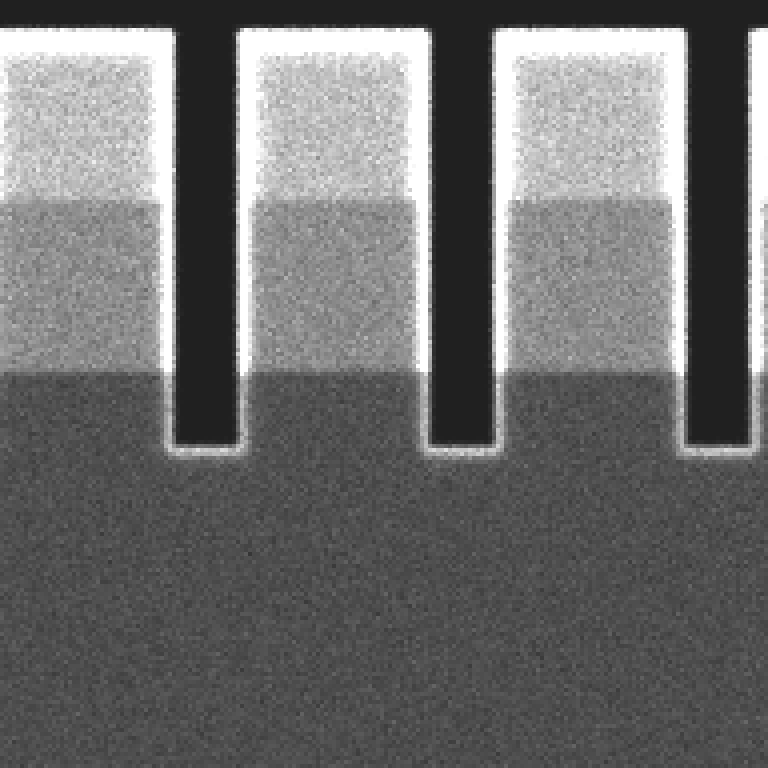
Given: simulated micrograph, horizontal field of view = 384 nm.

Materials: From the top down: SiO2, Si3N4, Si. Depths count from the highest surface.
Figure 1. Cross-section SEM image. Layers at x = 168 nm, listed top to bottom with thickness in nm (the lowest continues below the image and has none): SiO2 84, Si3N4 86, Si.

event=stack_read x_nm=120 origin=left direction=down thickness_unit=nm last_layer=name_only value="SiO2 84, Si3N4 86, Si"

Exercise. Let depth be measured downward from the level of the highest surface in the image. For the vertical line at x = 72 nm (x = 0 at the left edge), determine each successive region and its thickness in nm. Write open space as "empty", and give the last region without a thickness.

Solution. SiO2 84, Si3N4 86, Si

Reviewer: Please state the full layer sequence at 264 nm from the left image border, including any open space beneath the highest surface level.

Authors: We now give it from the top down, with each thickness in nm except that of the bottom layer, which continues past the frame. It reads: SiO2 84, Si3N4 86, Si